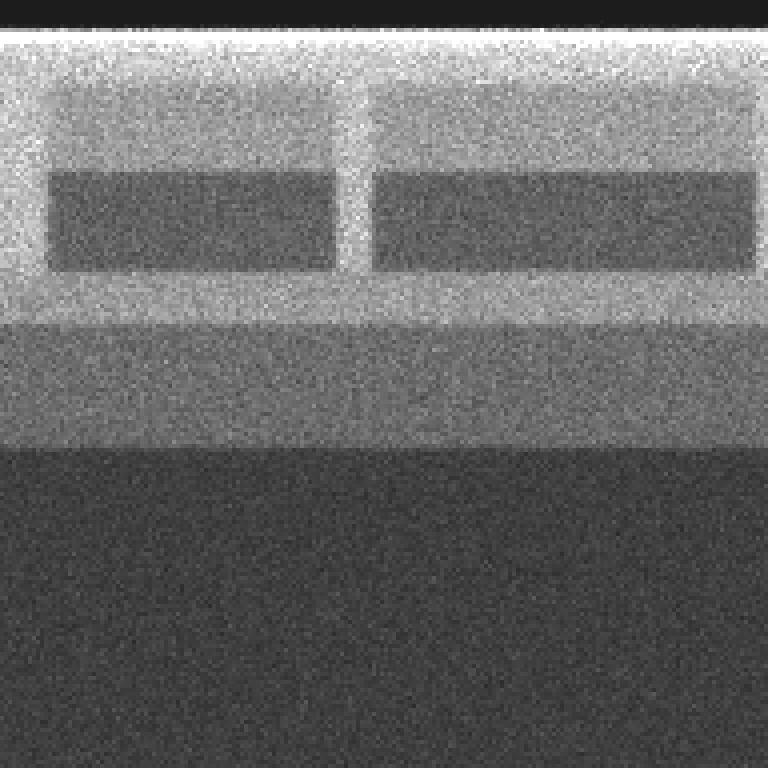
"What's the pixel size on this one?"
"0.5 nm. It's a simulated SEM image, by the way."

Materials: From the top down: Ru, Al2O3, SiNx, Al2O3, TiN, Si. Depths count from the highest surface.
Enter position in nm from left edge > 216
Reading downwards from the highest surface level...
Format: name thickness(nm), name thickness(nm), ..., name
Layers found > Ru 26, Al2O3 44, SiNx 50, Al2O3 26, TiN 62, Si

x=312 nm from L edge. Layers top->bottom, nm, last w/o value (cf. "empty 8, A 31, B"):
Ru 26, Al2O3 44, SiNx 50, Al2O3 26, TiN 62, Si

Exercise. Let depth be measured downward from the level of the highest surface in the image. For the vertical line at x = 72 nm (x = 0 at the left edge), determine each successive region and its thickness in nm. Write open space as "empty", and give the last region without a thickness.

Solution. Ru 26, Al2O3 44, SiNx 50, Al2O3 26, TiN 62, Si